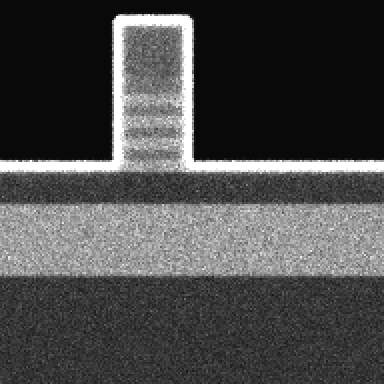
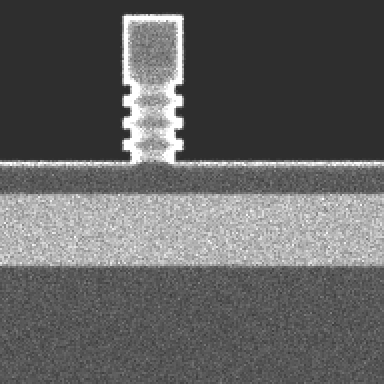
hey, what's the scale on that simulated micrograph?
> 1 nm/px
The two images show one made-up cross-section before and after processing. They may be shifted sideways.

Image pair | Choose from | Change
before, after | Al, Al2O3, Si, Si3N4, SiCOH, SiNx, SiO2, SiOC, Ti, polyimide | Al2O3 (removed)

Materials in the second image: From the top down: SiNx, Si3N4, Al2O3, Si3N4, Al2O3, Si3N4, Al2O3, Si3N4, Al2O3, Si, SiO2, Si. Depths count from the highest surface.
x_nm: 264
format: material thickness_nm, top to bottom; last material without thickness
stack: empty 146, Si 32, SiO2 72, Si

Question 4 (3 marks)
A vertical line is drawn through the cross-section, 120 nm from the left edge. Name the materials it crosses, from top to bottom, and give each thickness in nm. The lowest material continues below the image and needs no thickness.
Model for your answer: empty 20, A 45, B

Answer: empty 146, Si 32, SiO2 72, Si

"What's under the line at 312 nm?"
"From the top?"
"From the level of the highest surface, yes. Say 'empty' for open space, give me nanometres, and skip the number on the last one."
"empty 146, Si 32, SiO2 72, Si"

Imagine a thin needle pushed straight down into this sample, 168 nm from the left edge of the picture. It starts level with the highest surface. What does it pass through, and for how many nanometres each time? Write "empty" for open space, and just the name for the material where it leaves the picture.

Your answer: SiNx 50, Si3N4 18, Al2O3 12, Si3N4 10, Al2O3 12, Si3N4 10, Al2O3 12, Si3N4 10, Al2O3 12, Si 32, SiO2 72, Si